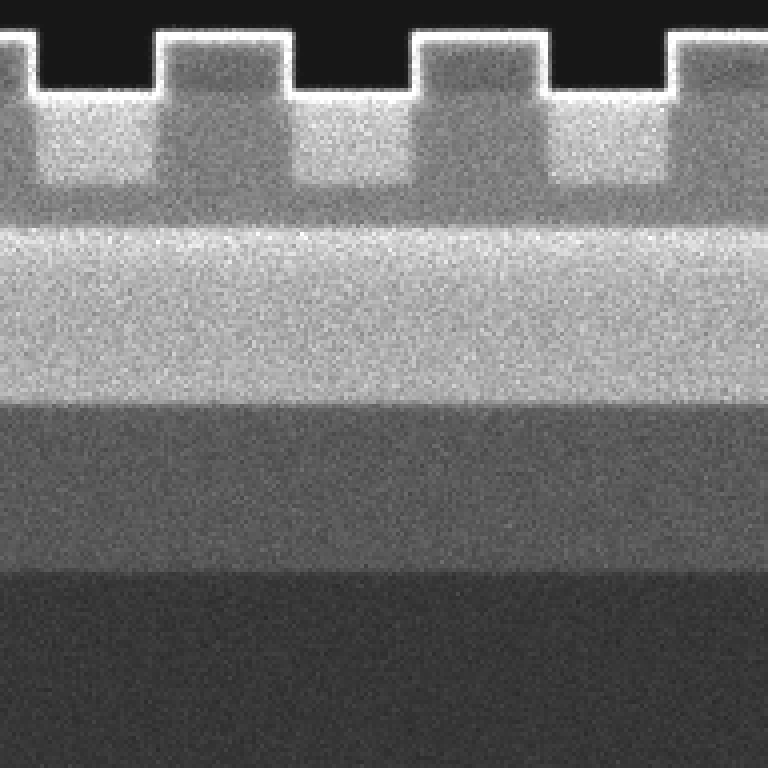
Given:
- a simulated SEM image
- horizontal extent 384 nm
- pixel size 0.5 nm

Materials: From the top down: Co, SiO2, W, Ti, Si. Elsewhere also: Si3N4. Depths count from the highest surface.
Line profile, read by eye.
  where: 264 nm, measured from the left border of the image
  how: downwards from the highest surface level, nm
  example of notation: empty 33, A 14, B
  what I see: Si3N4 30, SiO2 68, W 88, Ti 84, Si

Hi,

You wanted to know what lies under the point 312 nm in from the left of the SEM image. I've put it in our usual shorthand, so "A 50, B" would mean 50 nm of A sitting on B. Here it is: empty 30, Co 46, SiO2 22, W 88, Ti 84, Si